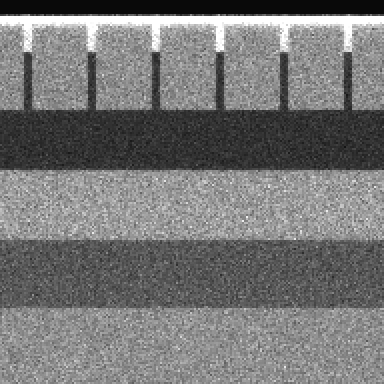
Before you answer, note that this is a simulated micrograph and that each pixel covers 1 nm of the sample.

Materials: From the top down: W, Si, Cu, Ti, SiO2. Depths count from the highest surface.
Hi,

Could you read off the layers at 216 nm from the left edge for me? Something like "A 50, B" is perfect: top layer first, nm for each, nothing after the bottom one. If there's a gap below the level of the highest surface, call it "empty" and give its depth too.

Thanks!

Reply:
W 36, Si 118, Cu 70, Ti 68, SiO2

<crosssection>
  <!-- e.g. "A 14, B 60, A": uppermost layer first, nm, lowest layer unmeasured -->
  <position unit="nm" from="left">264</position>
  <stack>SiO2 94, Si 60, Cu 70, Ti 68, SiO2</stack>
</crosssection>